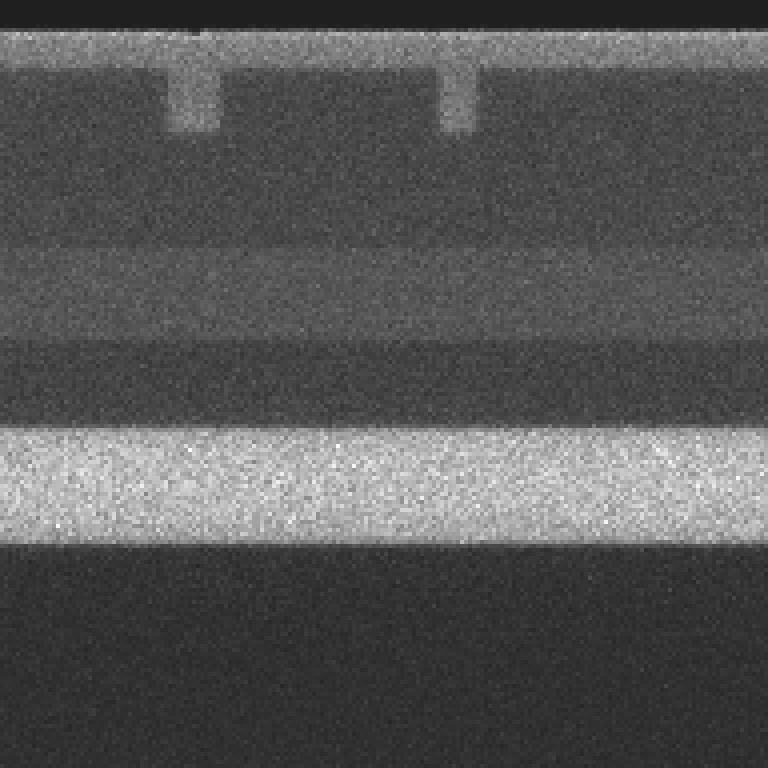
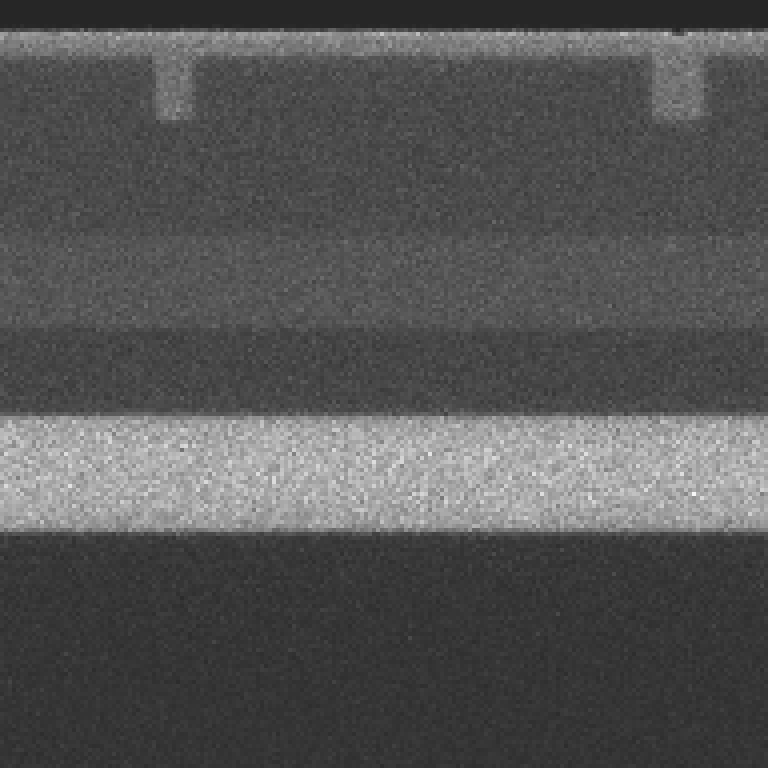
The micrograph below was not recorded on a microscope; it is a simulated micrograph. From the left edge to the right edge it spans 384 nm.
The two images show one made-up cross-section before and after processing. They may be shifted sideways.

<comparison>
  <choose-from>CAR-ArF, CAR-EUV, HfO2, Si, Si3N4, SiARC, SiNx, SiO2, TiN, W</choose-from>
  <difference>W removed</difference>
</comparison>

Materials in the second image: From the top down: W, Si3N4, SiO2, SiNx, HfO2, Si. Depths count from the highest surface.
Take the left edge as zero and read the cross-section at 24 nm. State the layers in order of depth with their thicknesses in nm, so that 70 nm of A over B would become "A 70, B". W 12, Si3N4 90, SiO2 46, SiNx 44, HfO2 58, Si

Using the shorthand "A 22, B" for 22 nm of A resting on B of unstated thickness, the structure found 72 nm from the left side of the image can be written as W 12, Si3N4 90, SiO2 46, SiNx 44, HfO2 58, Si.